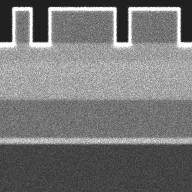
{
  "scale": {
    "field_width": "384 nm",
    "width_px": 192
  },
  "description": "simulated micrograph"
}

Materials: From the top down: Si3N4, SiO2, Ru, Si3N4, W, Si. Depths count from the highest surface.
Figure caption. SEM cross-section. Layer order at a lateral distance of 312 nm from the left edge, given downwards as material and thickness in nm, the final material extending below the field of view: Si3N4 70, SiO2 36, Ru 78, Si3N4 76, W 12, Si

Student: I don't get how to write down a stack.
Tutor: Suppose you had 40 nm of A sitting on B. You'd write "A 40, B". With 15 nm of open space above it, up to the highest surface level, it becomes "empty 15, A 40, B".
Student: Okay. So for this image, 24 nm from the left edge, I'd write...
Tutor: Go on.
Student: empty 70, SiO2 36, Ru 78, Si3N4 76, W 12, Si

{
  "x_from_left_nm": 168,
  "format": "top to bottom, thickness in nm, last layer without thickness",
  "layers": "Si3N4 70, SiO2 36, Ru 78, Si3N4 76, W 12, Si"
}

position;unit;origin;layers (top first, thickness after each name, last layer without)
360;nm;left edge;empty 70, SiO2 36, Ru 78, Si3N4 76, W 12, Si